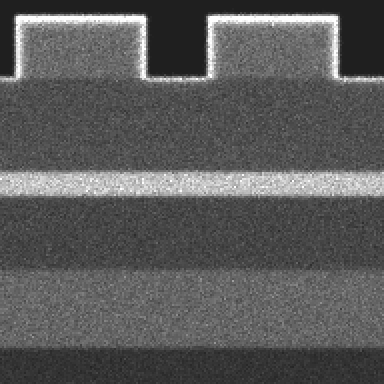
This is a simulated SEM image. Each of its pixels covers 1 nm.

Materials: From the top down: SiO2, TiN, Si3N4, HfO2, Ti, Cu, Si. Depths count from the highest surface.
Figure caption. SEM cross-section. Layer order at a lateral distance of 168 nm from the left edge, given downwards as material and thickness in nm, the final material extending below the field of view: empty 62, TiN 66, Si3N4 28, HfO2 24, Ti 74, Cu 78, Si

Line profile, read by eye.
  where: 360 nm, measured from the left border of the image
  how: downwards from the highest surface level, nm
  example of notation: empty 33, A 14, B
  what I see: empty 62, TiN 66, Si3N4 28, HfO2 24, Ti 74, Cu 78, Si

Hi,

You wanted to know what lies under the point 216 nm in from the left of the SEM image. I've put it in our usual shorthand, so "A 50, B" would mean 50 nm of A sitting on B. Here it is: SiO2 62, TiN 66, Si3N4 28, HfO2 24, Ti 74, Cu 78, Si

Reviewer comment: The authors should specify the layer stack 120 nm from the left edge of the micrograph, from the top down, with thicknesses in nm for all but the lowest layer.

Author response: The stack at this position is SiO2 62, TiN 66, Si3N4 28, HfO2 24, Ti 74, Cu 78, Si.